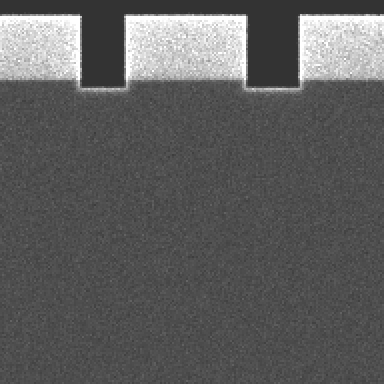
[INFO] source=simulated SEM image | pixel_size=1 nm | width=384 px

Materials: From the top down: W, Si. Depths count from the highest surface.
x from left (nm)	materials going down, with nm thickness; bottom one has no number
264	empty 72, Si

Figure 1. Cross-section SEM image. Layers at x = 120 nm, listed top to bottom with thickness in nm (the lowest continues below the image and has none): empty 72, Si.